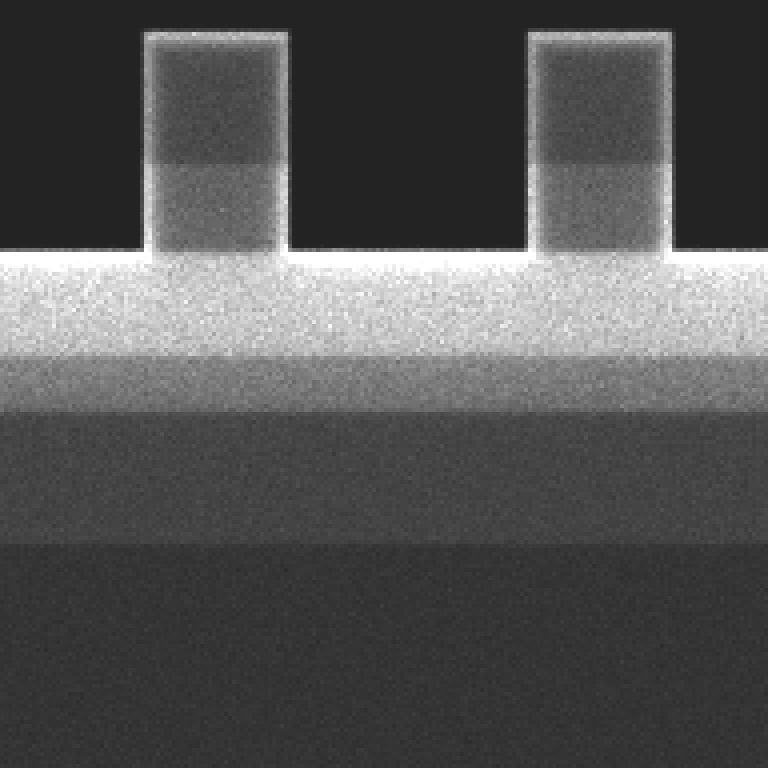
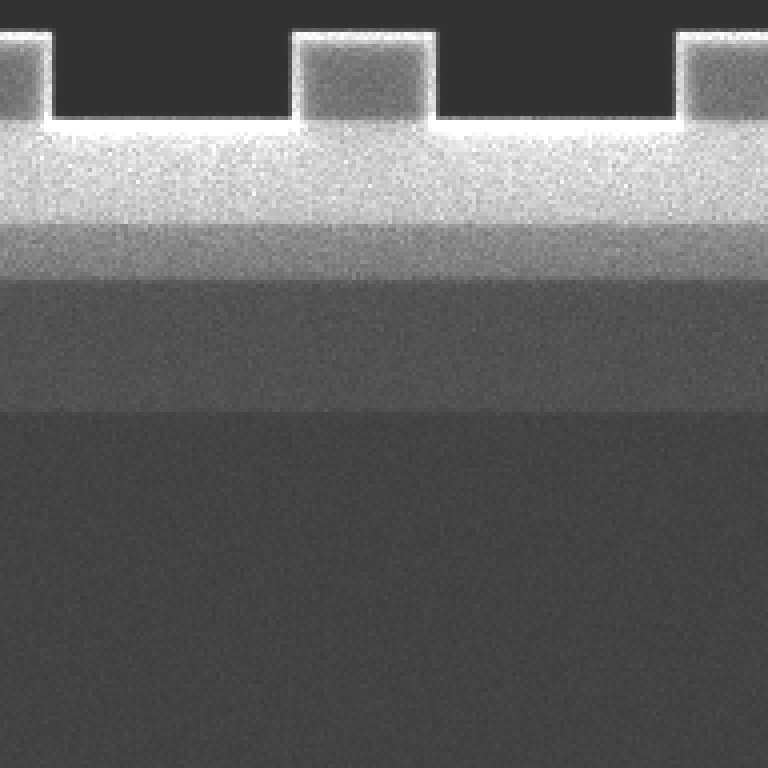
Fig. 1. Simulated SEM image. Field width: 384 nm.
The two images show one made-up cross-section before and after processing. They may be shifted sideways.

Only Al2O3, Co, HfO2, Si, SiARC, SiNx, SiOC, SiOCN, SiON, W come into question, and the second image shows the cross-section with SiARC removed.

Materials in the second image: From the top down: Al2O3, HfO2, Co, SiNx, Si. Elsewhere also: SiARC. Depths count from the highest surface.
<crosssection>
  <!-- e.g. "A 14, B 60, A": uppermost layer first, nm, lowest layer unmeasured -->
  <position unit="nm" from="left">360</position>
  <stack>Al2O3 44, HfO2 52, Co 28, SiNx 66, Si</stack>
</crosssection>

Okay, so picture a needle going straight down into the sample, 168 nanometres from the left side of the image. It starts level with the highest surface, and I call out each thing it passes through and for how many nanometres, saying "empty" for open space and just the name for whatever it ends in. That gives Al2O3 44, HfO2 52, Co 28, SiNx 66, Si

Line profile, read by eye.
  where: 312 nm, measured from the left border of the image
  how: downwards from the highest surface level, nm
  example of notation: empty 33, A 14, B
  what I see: empty 44, HfO2 52, Co 28, SiNx 66, Si